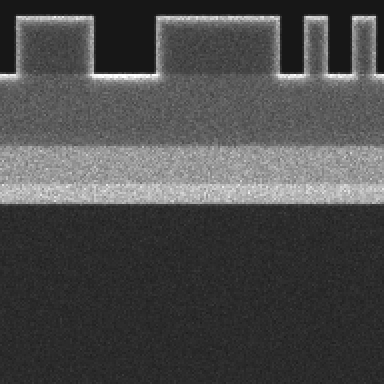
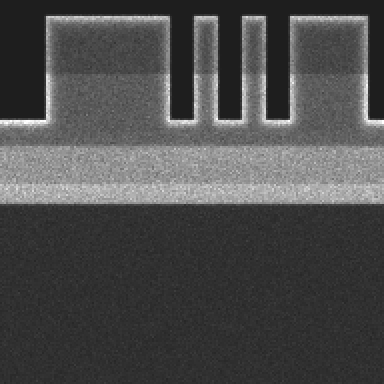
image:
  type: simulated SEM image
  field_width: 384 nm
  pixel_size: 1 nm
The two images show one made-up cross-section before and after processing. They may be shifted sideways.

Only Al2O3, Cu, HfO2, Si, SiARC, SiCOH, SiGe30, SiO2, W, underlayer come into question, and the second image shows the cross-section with SiO2 removed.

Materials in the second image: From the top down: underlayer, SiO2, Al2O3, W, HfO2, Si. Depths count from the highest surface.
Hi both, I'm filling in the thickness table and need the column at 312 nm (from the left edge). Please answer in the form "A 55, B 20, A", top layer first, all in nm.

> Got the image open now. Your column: underlayer 58, SiO2 58, Al2O3 14, W 38, HfO2 20, Si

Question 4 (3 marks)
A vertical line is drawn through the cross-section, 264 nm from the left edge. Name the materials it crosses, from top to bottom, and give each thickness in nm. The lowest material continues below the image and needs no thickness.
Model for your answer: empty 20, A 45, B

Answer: underlayer 58, SiO2 58, Al2O3 14, W 38, HfO2 20, Si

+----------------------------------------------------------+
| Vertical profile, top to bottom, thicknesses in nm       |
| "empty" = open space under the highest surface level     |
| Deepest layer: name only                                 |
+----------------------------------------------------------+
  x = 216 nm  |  underlayer 58, SiO2 58, Al2O3 14, W 38, HfO2 20, Si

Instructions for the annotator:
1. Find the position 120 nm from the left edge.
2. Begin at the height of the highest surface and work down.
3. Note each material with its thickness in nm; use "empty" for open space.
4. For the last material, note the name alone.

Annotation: underlayer 58, SiO2 58, Al2O3 14, W 38, HfO2 20, Si